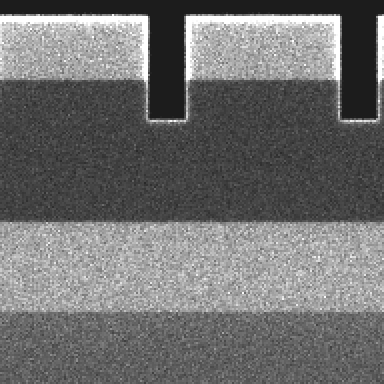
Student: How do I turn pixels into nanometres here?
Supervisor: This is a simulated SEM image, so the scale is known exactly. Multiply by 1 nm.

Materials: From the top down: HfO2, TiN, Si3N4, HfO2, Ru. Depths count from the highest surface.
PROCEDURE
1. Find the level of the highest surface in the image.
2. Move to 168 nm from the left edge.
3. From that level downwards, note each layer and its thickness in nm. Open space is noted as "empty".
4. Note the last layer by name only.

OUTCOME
empty 104, TiN 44, Si3N4 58, HfO2 90, Ru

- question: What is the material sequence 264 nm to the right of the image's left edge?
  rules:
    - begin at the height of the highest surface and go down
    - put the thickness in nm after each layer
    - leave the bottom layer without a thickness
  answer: HfO2 64, TiN 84, Si3N4 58, HfO2 90, Ru